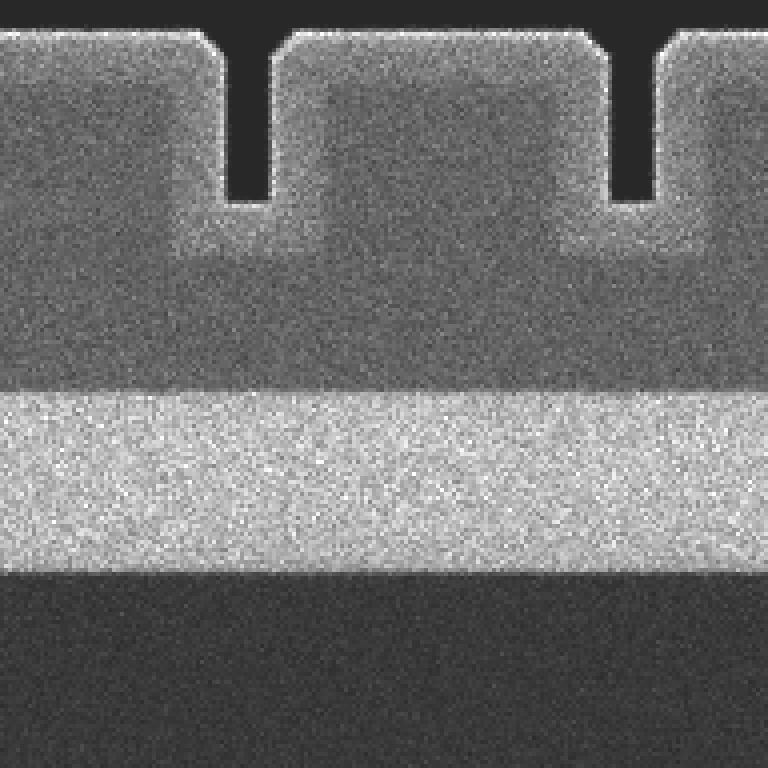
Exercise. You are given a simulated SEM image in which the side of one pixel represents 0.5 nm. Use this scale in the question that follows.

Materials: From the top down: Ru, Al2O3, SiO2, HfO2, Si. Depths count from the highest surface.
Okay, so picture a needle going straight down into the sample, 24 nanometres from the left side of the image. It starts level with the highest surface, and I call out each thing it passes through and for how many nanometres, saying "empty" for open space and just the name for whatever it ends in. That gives Ru 26, Al2O3 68, SiO2 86, HfO2 90, Si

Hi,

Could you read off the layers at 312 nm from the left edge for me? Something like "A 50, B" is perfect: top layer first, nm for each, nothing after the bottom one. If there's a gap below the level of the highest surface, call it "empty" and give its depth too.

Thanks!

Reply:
empty 86, Ru 26, SiO2 68, HfO2 90, Si